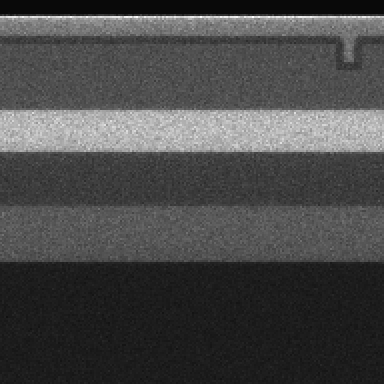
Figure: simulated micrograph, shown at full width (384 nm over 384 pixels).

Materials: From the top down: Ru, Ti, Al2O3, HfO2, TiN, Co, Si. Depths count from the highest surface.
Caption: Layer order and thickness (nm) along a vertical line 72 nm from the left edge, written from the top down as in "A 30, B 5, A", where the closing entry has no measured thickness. Ru 20, Ti 8, Al2O3 66, HfO2 42, TiN 54, Co 56, Si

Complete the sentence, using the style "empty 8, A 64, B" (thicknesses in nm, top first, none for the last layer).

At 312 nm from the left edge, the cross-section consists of Ru 20, Ti 8, Al2O3 66, HfO2 42, TiN 54, Co 56, Si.